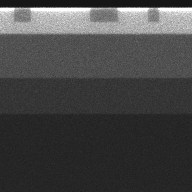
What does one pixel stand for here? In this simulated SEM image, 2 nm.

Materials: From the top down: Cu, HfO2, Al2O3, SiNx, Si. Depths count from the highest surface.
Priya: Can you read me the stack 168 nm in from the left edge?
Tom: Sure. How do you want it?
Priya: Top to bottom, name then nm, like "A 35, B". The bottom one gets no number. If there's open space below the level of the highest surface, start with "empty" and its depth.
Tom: HfO2 52, Al2O3 88, SiNx 72, Si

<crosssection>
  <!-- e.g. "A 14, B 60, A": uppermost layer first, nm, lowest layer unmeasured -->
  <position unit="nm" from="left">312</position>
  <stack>Cu 28, HfO2 24, Al2O3 88, SiNx 72, Si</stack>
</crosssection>